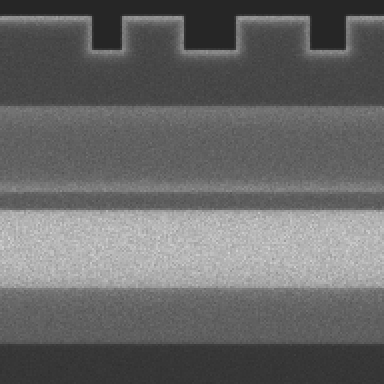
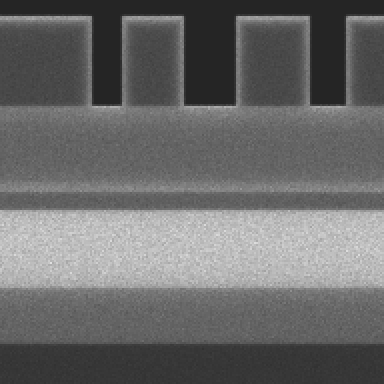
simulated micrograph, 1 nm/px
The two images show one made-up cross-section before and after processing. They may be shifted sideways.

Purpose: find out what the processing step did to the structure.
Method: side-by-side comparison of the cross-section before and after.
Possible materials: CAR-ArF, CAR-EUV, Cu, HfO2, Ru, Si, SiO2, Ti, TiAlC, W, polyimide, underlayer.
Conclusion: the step removed underlayer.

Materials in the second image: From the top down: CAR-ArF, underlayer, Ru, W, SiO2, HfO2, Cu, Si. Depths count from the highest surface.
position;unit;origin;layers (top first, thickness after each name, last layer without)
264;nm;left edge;CAR-ArF 34, underlayer 56, Ru 76, W 10, SiO2 18, HfO2 78, Cu 56, Si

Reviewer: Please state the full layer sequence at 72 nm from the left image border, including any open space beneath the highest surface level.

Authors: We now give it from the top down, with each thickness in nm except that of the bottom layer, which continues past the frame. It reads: CAR-ArF 34, underlayer 56, Ru 76, W 10, SiO2 18, HfO2 78, Cu 56, Si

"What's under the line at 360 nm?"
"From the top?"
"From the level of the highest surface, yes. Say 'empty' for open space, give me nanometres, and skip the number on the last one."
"CAR-ArF 34, underlayer 56, Ru 76, W 10, SiO2 18, HfO2 78, Cu 56, Si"